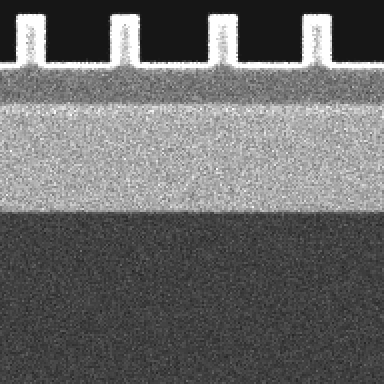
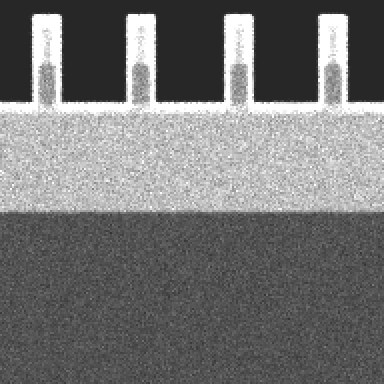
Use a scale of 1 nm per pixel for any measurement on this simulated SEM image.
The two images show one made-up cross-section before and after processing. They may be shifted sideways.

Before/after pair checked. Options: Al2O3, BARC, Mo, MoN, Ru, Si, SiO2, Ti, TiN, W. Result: removed TiN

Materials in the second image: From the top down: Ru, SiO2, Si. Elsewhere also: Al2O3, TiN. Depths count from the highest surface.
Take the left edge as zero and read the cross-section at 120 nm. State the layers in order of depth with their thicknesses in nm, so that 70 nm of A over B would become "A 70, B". empty 88, Ru 10, SiO2 98, Si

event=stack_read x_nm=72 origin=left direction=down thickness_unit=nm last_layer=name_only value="empty 88, Ru 10, SiO2 98, Si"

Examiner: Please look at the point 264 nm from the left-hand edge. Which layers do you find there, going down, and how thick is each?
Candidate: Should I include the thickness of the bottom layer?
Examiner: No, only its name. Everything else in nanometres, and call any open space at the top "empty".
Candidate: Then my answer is empty 88, Ru 10, SiO2 98, Si